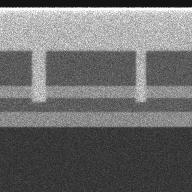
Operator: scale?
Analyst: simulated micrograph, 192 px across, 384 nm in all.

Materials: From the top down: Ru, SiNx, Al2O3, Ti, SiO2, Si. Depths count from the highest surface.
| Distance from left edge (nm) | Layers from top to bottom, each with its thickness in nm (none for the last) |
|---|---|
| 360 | Ru 86, SiNx 70, Al2O3 24, Ti 28, SiO2 30, Si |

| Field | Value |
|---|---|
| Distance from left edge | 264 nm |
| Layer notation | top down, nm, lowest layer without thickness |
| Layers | Ru 86, SiNx 70, Al2O3 24, Ti 28, SiO2 30, Si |